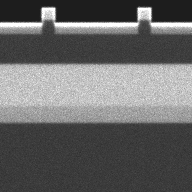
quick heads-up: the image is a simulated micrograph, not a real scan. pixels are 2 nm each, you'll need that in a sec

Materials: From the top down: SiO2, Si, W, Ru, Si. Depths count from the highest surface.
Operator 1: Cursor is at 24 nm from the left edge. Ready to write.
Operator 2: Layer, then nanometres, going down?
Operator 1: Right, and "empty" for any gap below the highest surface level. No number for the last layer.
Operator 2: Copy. empty 30, SiO2 22, Si 60, W 84, Ru 34, Si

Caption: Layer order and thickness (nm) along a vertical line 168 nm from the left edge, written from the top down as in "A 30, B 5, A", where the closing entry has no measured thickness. empty 30, SiO2 22, Si 60, W 84, Ru 34, Si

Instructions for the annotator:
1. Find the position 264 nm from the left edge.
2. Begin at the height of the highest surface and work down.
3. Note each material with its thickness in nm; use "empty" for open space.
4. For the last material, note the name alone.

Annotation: empty 30, SiO2 22, Si 60, W 84, Ru 34, Si